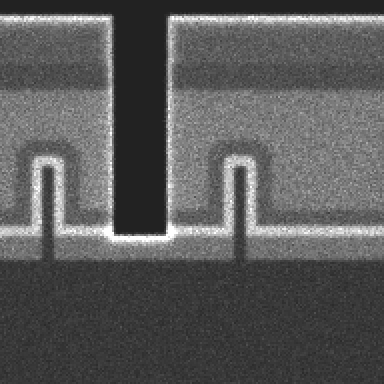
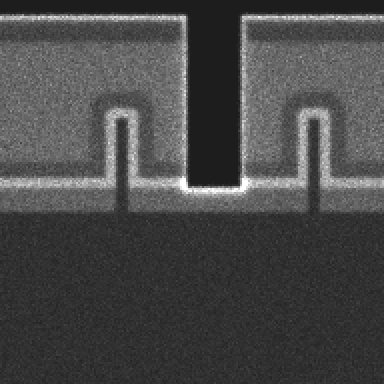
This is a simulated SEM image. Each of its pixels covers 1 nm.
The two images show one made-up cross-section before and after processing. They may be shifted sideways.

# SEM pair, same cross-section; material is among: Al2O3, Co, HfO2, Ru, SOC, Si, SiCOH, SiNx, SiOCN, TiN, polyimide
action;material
removed;SOC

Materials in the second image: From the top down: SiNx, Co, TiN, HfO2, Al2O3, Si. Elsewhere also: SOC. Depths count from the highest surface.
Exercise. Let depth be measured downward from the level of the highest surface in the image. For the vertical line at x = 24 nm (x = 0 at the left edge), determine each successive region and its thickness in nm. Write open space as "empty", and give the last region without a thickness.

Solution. SiNx 26, Co 120, TiN 16, HfO2 10, Al2O3 24, Si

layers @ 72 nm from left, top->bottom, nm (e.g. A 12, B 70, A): SiNx 26, Co 120, TiN 16, HfO2 10, Al2O3 24, Si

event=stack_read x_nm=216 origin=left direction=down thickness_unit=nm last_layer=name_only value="empty 172, Al2O3 24, Si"